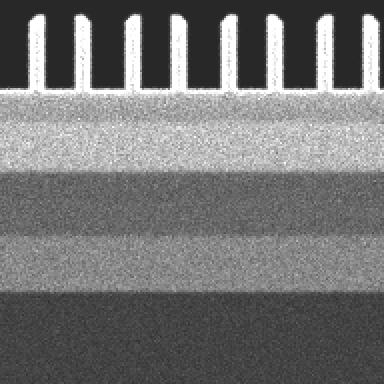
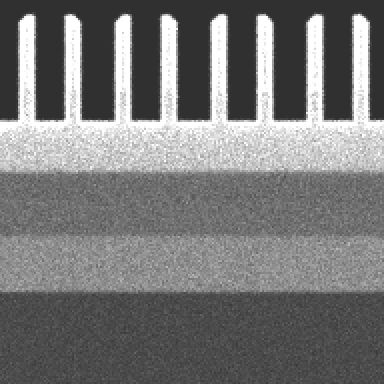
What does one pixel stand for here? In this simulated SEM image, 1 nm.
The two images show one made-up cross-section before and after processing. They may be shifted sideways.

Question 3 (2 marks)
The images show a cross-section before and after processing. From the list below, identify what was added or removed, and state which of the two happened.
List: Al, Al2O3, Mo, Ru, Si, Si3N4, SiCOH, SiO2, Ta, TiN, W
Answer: Ru was removed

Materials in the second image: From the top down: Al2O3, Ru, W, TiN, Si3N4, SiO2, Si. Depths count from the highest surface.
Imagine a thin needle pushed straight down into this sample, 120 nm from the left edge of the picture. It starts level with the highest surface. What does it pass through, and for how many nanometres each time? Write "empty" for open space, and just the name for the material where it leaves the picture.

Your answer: empty 2, Al2O3 72, Ru 32, W 50, TiN 28, Si3N4 36, SiO2 56, Si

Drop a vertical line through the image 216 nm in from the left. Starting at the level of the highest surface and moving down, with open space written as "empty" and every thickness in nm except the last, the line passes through empty 2, Al2O3 72, Ru 32, W 50, TiN 28, Si3N4 36, SiO2 56, Si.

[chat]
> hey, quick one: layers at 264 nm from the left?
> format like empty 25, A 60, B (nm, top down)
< Al2O3 74, Ru 32, W 50, TiN 28, Si3N4 36, SiO2 56, Si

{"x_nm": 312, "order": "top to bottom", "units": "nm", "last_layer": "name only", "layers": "empty 2, Al2O3 72, Ru 32, W 50, TiN 28, Si3N4 36, SiO2 56, Si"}